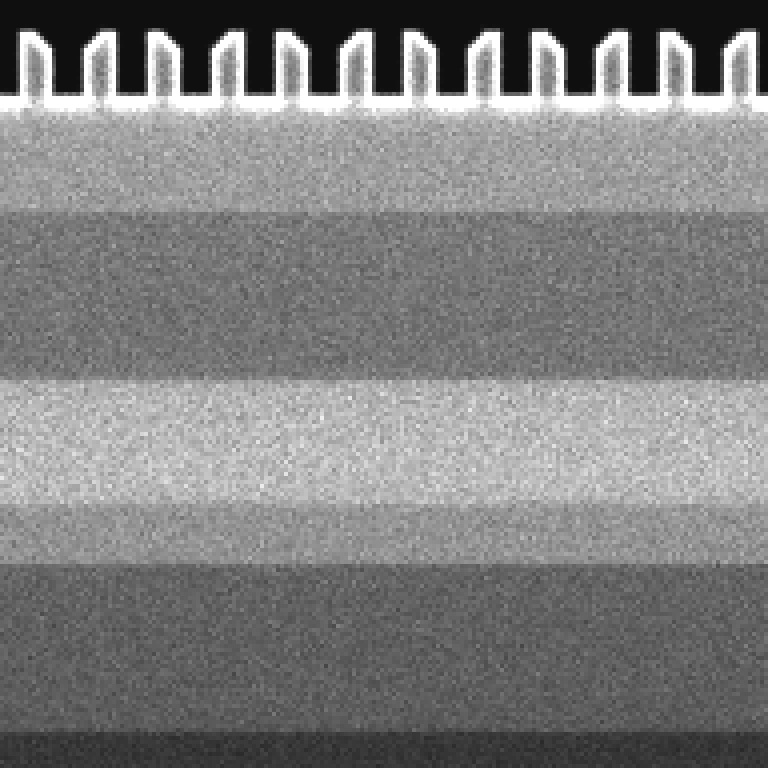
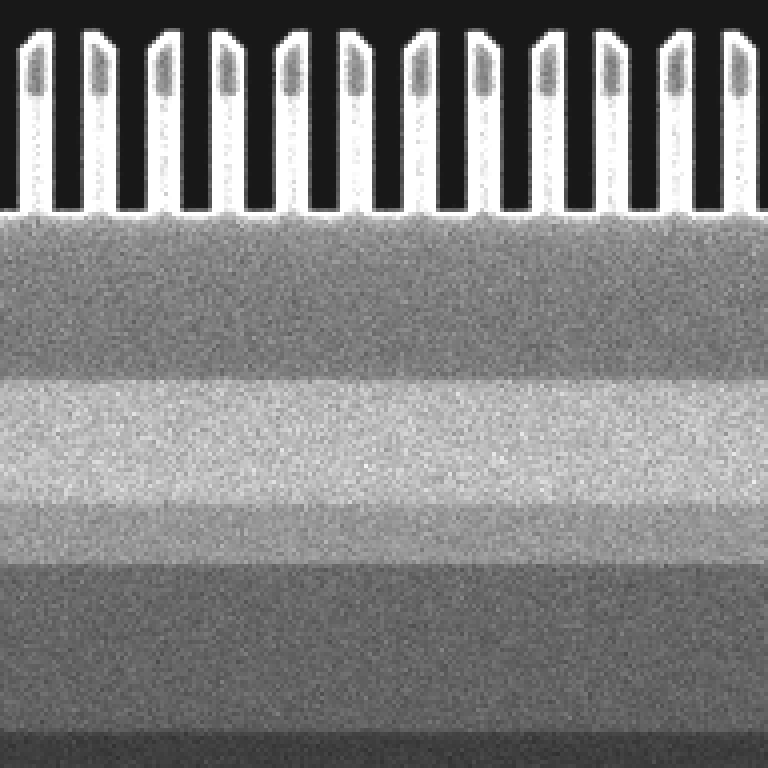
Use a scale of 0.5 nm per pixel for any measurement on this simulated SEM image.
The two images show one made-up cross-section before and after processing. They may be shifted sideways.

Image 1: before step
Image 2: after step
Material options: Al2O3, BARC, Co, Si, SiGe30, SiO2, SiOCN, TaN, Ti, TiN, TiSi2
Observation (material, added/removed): Al2O3, removed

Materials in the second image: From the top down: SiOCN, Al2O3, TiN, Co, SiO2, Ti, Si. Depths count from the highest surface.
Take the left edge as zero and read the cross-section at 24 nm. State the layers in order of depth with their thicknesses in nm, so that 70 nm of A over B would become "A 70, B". SiOCN 32, Al2O3 58, TiN 84, Co 62, SiO2 30, Ti 84, Si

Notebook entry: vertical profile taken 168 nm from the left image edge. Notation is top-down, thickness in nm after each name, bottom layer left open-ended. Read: empty 90, TiN 84, Co 62, SiO2 30, Ti 84, Si